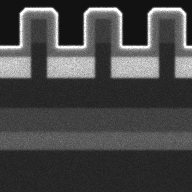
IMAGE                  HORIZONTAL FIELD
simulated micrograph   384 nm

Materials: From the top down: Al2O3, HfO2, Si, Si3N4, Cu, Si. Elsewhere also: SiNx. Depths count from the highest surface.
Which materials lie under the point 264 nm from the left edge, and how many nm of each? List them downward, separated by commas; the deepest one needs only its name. empty 76, Al2O3 22, HfO2 42, Si 60, Si3N4 48, Cu 36, Si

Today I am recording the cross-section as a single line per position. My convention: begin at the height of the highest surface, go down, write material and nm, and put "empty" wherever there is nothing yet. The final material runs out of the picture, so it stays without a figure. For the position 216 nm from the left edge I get Al2O3 22, SiNx 48, Si 130, Si3N4 48, Cu 36, Si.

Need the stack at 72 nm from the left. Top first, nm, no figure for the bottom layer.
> Al2O3 22, SiNx 48, Si 130, Si3N4 48, Cu 36, Si